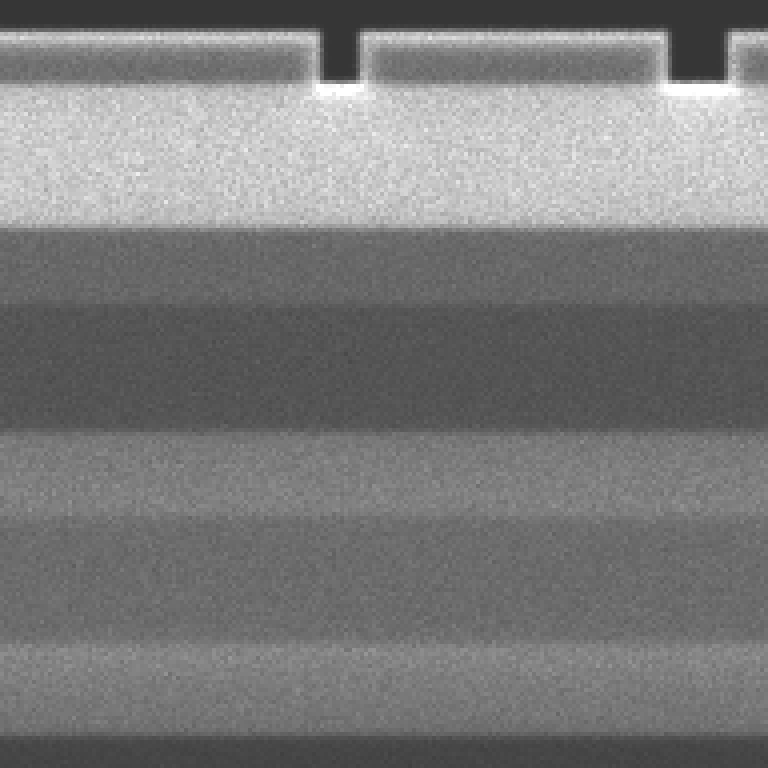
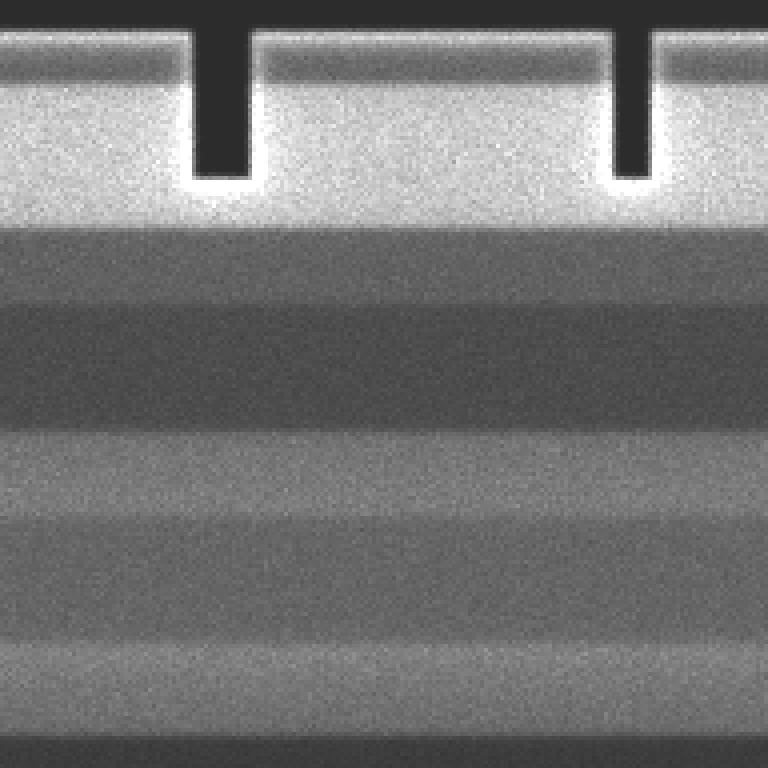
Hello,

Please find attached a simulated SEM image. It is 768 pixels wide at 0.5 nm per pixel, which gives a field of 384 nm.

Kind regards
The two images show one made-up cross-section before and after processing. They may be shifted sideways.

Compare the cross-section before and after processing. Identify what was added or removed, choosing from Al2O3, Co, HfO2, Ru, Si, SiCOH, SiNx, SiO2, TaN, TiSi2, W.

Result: HfO2 removed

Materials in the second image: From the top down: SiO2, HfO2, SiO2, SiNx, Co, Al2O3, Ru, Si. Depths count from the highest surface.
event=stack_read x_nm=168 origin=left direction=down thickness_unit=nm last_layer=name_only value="SiO2 26, HfO2 72, SiO2 38, SiNx 64, Co 42, Al2O3 64, Ru 46, Si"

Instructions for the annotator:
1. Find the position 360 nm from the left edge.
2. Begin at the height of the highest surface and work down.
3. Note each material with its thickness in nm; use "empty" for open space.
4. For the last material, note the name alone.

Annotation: SiO2 26, HfO2 72, SiO2 38, SiNx 64, Co 42, Al2O3 64, Ru 46, Si